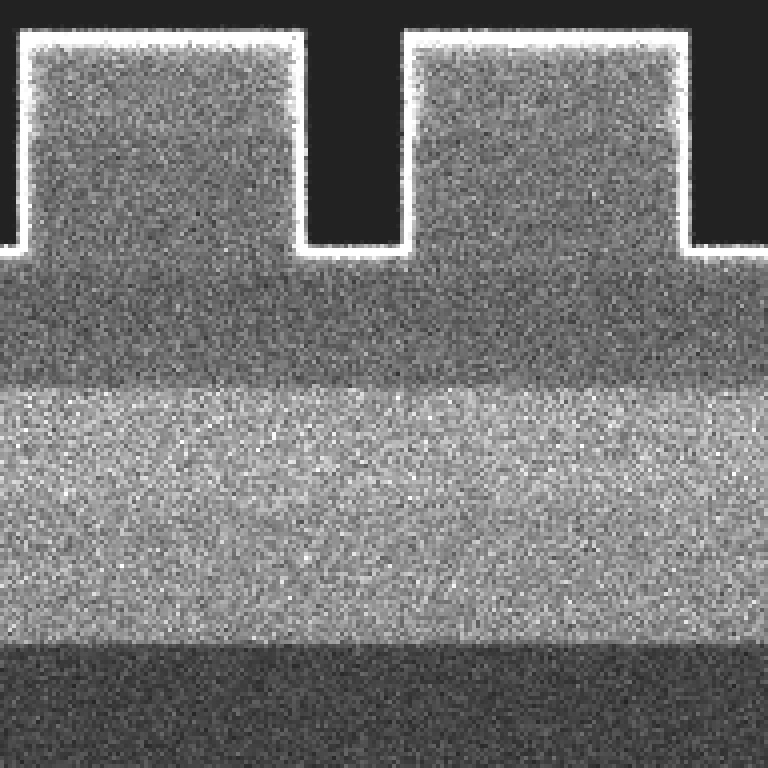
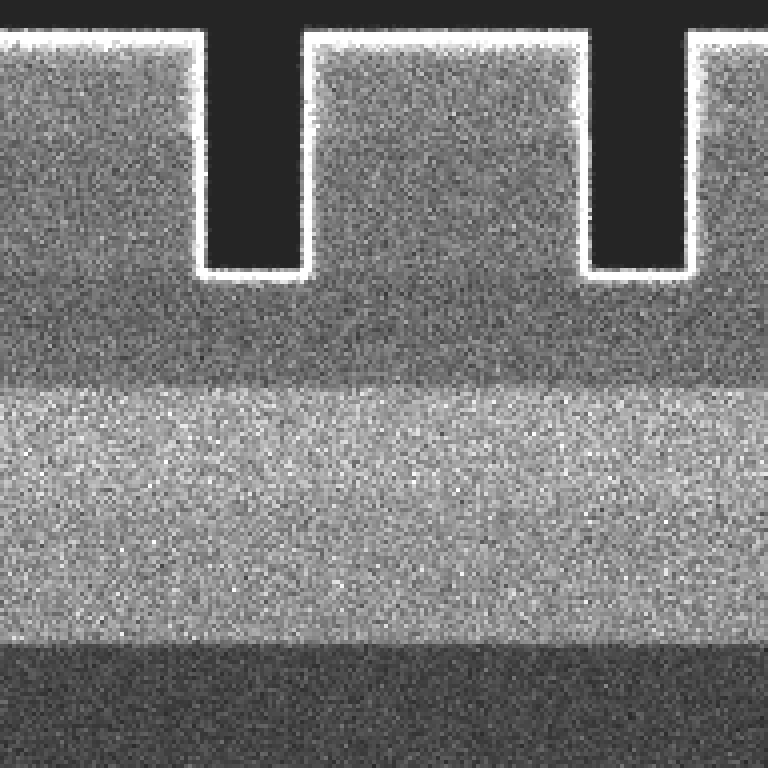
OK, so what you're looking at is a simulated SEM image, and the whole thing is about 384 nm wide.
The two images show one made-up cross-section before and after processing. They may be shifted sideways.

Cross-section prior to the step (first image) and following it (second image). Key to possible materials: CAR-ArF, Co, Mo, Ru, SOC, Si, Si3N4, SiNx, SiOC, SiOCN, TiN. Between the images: Si3N4 was removed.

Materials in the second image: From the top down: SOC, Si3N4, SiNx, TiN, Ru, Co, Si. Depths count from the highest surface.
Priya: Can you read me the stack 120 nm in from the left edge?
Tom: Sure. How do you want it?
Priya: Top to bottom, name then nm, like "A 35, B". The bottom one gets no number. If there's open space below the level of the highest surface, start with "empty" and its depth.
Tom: empty 120, SiNx 34, TiN 24, Ru 56, Co 72, Si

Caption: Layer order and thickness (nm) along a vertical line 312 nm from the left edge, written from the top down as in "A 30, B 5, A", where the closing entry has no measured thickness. empty 120, SiNx 34, TiN 24, Ru 56, Co 72, Si